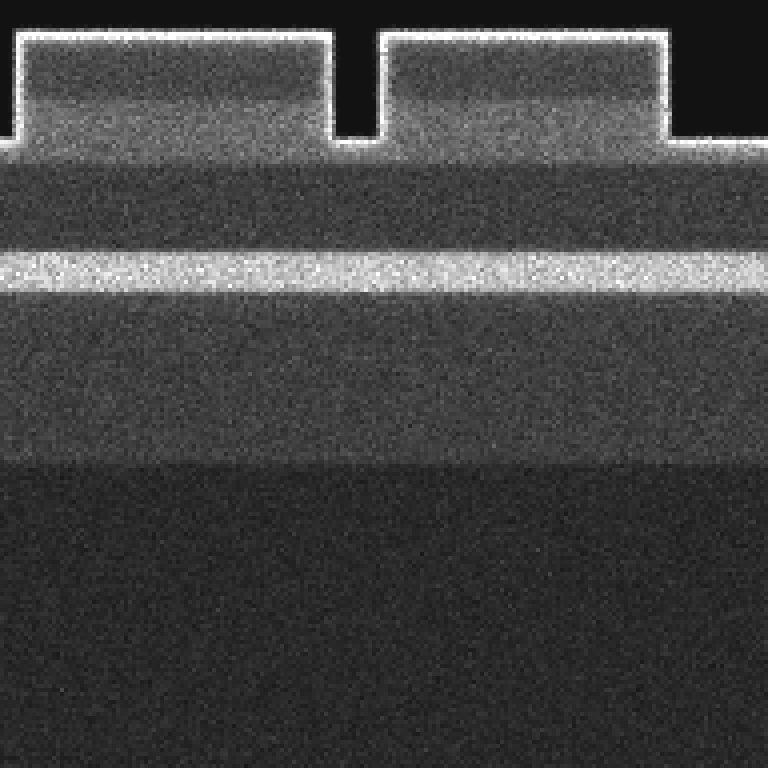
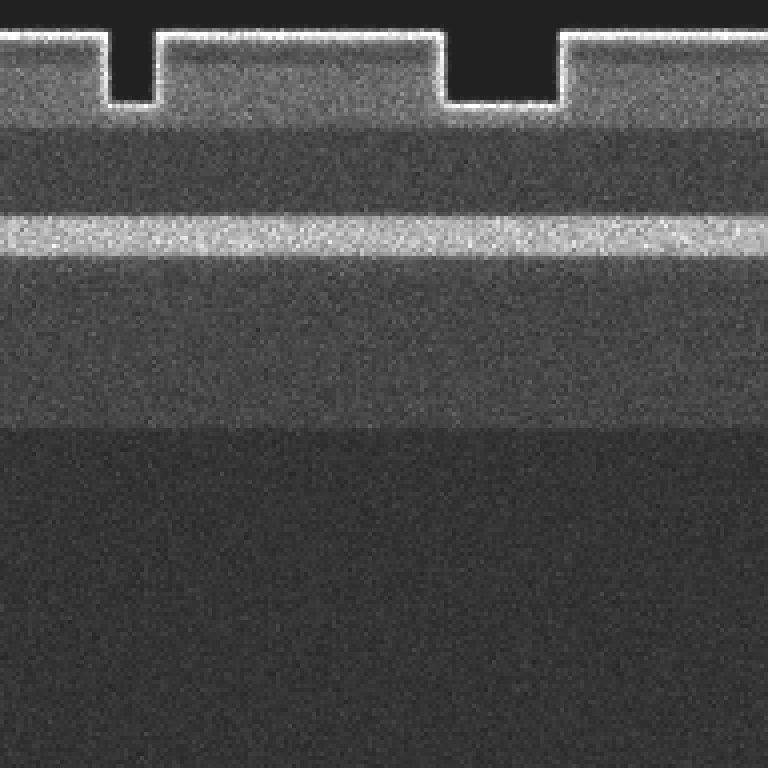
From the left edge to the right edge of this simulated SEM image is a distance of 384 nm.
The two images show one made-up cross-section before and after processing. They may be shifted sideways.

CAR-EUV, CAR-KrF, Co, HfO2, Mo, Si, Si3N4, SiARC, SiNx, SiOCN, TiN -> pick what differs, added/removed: Si3N4 removed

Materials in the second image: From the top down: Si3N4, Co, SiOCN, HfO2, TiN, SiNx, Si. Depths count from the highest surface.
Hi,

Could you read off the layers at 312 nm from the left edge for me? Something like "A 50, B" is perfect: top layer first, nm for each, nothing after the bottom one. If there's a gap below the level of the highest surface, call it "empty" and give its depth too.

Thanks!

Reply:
Si3N4 16, Co 32, SiOCN 44, HfO2 20, TiN 10, SiNx 76, Si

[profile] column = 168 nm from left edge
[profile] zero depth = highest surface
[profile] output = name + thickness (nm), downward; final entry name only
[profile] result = Si3N4 16, Co 32, SiOCN 44, HfO2 20, TiN 10, SiNx 76, Si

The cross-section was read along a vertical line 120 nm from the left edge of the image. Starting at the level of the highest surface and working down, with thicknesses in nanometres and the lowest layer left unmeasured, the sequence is Si3N4 16, Co 32, SiOCN 44, HfO2 20, TiN 10, SiNx 76, Si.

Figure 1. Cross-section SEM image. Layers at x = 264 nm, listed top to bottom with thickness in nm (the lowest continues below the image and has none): empty 36, Co 12, SiOCN 44, HfO2 20, TiN 10, SiNx 76, Si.